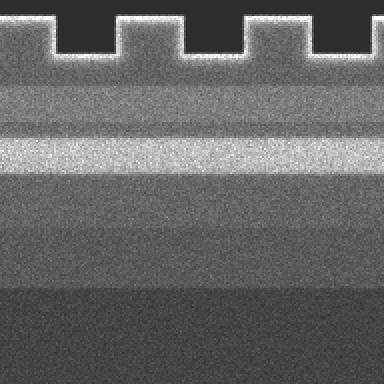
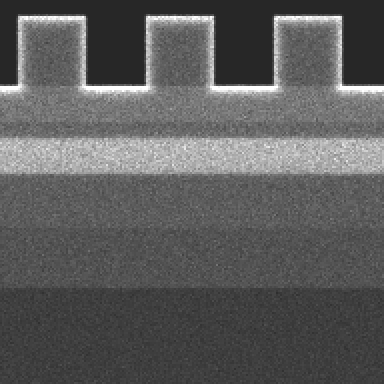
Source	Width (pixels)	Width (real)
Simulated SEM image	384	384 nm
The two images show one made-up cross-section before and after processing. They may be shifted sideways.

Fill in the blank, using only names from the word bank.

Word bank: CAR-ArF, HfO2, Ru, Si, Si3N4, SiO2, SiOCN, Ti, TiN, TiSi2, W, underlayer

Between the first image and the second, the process removed underlayer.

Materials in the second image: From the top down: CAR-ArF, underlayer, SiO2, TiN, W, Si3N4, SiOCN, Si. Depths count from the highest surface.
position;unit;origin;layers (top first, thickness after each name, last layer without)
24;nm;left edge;CAR-ArF 38, underlayer 32, SiO2 36, TiN 16, W 36, Si3N4 54, SiOCN 60, Si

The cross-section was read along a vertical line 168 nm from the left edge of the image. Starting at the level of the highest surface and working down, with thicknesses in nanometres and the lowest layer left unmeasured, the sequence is CAR-ArF 38, underlayer 32, SiO2 36, TiN 16, W 36, Si3N4 54, SiOCN 60, Si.